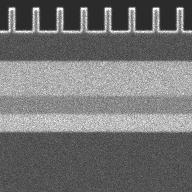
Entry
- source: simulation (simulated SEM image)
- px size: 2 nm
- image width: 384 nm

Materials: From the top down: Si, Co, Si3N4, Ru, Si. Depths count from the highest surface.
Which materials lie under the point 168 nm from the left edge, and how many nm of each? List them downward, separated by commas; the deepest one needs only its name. Si 106, Co 70, Si3N4 36, Ru 36, Si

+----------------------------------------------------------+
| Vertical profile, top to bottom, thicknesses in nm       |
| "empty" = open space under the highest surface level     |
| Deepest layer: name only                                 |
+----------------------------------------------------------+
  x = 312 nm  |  Si 106, Co 70, Si3N4 36, Ru 36, Si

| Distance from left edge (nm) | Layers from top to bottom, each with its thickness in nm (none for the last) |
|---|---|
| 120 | Si 106, Co 70, Si3N4 36, Ru 36, Si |